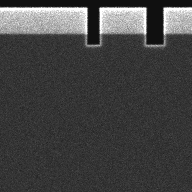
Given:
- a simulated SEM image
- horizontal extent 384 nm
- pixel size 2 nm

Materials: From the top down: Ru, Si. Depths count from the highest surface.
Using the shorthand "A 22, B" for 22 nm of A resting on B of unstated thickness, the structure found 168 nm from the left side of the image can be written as Ru 52, Si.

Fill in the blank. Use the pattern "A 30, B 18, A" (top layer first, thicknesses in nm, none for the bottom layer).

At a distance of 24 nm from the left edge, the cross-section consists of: Ru 52, Si